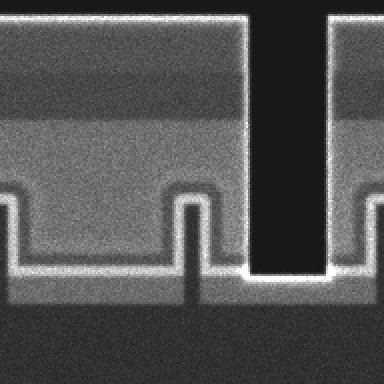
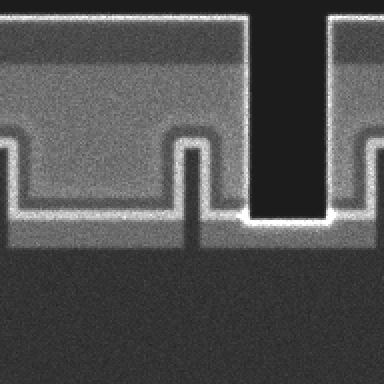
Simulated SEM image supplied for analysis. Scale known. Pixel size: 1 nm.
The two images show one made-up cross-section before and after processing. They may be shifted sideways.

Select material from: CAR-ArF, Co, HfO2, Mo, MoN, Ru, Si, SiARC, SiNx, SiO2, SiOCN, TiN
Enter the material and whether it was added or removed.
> SiARC / removed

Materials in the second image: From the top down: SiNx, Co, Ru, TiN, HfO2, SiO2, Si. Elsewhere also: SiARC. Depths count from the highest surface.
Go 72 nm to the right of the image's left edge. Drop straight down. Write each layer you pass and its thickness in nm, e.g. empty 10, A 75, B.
SiNx 48, Co 122, Ru 12, TiN 12, HfO2 10, SiO2 28, Si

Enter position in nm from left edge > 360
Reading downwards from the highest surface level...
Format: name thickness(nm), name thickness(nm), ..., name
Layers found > SiNx 48, Co 50, Ru 16, TiN 80, HfO2 10, SiO2 28, Si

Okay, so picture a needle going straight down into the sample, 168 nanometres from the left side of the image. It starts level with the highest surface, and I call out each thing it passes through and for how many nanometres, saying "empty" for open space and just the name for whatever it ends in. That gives SiNx 48, Co 50, Ru 16, TiN 80, HfO2 10, SiO2 28, Si